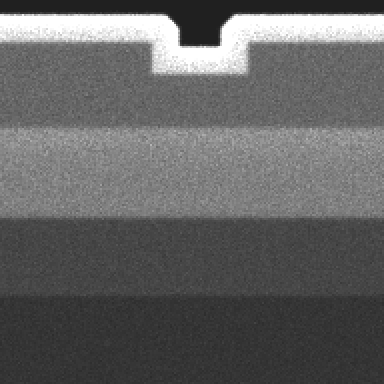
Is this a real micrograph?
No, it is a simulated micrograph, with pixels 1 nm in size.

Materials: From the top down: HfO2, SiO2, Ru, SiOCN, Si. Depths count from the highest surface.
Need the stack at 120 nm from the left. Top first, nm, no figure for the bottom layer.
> HfO2 26, SiO2 86, Ru 90, SiOCN 78, Si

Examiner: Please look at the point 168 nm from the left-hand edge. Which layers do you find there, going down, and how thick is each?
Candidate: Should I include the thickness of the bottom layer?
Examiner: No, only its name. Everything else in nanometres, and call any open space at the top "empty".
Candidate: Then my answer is empty 4, HfO2 54, SiO2 54, Ru 90, SiOCN 78, Si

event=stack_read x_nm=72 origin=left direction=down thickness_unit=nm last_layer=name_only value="HfO2 26, SiO2 86, Ru 90, SiOCN 78, Si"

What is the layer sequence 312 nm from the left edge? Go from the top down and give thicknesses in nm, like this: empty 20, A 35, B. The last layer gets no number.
HfO2 26, SiO2 86, Ru 90, SiOCN 78, Si